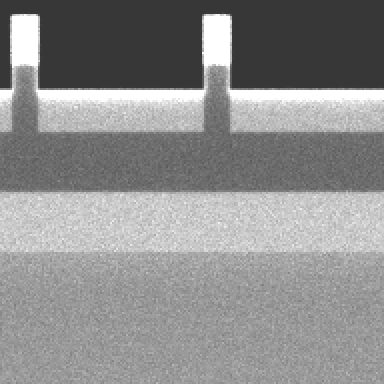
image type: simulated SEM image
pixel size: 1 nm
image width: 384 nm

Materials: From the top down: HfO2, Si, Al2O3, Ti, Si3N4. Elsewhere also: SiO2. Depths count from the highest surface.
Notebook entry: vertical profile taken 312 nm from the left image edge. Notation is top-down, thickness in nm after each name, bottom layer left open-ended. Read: empty 74, SiO2 42, Si 60, Al2O3 60, Ti 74, Si3N4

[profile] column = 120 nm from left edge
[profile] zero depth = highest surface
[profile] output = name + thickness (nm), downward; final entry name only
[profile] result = empty 74, SiO2 42, Si 60, Al2O3 60, Ti 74, Si3N4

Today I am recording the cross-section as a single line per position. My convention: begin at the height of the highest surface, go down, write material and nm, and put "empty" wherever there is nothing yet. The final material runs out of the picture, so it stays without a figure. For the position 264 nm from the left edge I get empty 74, SiO2 42, Si 60, Al2O3 60, Ti 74, Si3N4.